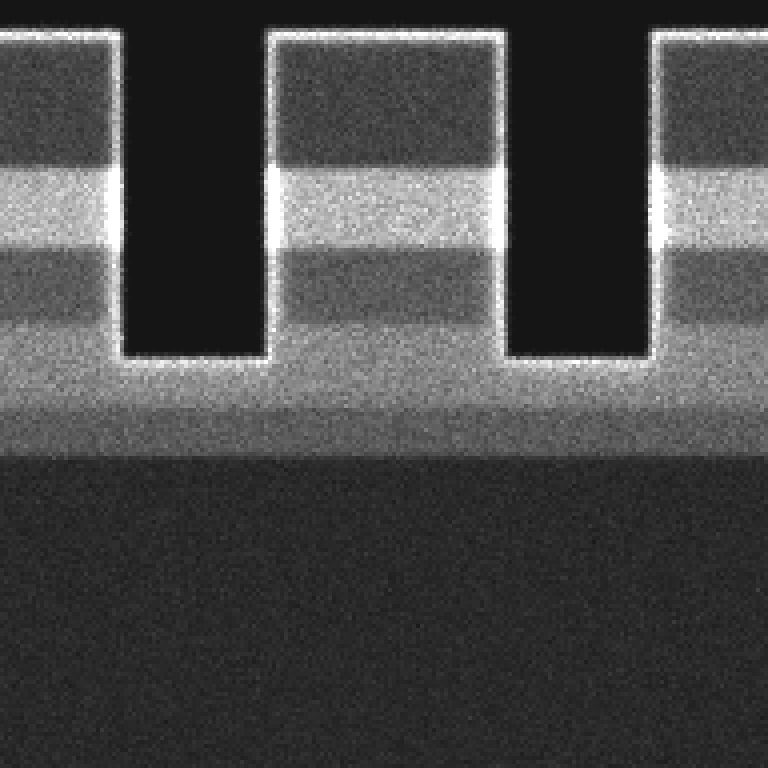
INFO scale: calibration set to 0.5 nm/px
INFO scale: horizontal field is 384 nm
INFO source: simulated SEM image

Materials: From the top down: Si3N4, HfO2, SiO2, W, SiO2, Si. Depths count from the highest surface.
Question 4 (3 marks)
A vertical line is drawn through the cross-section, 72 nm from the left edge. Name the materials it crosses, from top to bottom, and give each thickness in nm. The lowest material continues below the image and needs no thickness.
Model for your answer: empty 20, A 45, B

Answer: empty 164, W 24, SiO2 24, Si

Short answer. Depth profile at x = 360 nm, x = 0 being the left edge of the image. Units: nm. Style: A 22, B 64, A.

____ Si3N4 68, HfO2 40, SiO2 38, W 42, SiO2 24, Si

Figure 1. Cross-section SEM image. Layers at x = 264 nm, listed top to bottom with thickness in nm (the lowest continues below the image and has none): empty 164, W 24, SiO2 24, Si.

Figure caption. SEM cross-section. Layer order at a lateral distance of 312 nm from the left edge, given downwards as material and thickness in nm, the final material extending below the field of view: empty 164, W 24, SiO2 24, Si